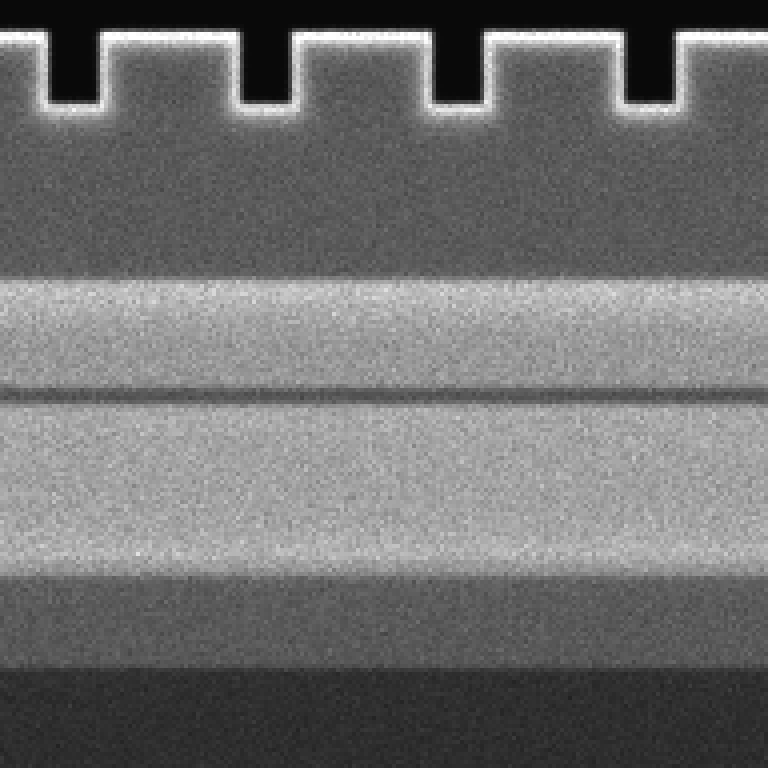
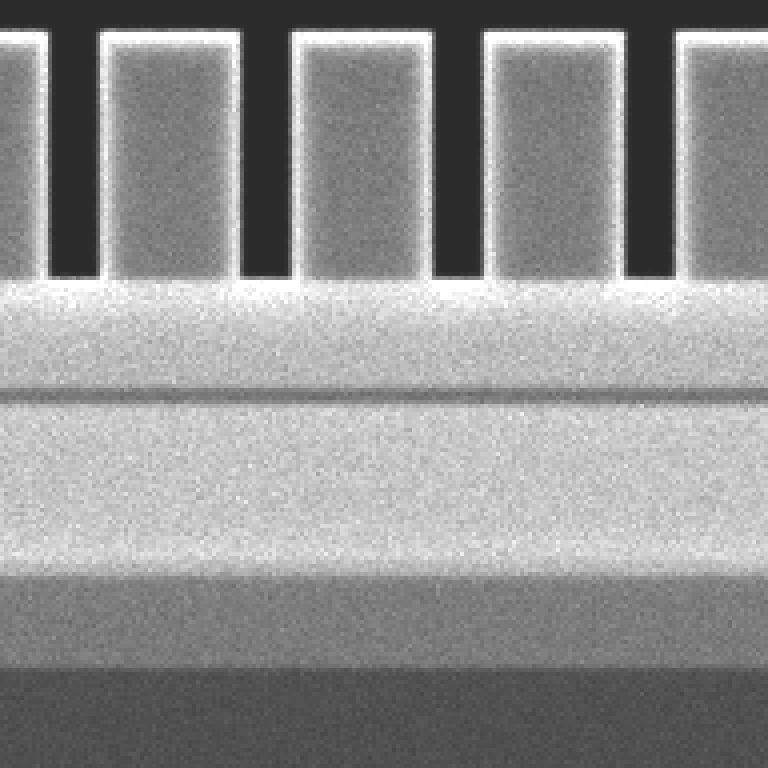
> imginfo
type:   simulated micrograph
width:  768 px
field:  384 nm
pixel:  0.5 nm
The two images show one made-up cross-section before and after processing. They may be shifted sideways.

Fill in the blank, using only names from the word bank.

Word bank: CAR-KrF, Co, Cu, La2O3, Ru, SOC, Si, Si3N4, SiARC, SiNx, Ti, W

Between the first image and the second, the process removed SOC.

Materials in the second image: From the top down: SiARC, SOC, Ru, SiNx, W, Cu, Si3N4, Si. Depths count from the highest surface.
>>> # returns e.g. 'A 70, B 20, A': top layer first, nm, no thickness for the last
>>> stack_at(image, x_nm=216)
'empty 124, Ru 54, SiNx 8, W 78, Cu 8, Si3N4 46, Si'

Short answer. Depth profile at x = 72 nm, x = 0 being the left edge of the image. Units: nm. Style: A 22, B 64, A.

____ SiARC 36, SOC 88, Ru 54, SiNx 8, W 78, Cu 8, Si3N4 46, Si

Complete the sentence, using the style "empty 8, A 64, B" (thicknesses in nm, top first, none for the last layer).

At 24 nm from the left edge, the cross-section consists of empty 124, Ru 54, SiNx 8, W 78, Cu 8, Si3N4 46, Si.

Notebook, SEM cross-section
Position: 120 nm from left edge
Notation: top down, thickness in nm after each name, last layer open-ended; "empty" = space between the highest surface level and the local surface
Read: empty 124, Ru 54, SiNx 8, W 78, Cu 8, Si3N4 46, Si